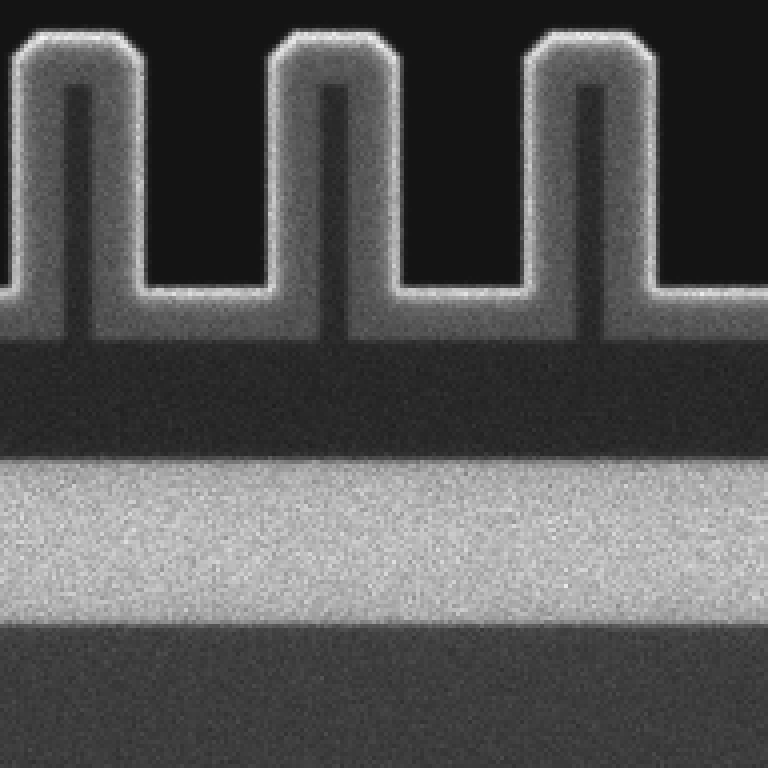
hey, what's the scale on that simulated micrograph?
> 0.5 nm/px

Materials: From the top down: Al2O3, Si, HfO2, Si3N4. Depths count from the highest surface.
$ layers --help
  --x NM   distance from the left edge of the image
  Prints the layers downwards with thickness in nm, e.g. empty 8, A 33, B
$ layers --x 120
empty 128, Al2O3 26, Si 60, HfO2 82, Si3N4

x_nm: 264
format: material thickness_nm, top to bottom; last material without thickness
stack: empty 10, Al2O3 144, Si 60, HfO2 82, Si3N4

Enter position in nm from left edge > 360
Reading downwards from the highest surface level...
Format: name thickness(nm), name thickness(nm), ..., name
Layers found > empty 128, Al2O3 26, Si 60, HfO2 82, Si3N4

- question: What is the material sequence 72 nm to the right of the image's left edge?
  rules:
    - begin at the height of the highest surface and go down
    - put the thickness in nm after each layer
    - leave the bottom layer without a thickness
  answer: empty 128, Al2O3 26, Si 60, HfO2 82, Si3N4